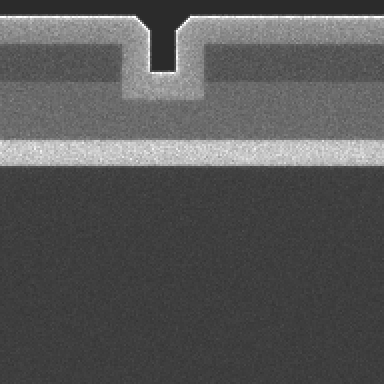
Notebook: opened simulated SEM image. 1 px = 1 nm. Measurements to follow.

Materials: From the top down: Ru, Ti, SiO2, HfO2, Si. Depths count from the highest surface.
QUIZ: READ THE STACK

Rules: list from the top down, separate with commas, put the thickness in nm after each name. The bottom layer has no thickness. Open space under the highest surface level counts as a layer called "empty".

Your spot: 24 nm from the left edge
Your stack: Ru 28, Ti 38, SiO2 58, HfO2 26, Si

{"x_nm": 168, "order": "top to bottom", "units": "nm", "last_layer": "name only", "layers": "empty 56, Ru 28, SiO2 40, HfO2 26, Si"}